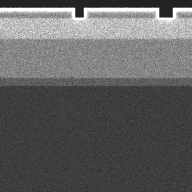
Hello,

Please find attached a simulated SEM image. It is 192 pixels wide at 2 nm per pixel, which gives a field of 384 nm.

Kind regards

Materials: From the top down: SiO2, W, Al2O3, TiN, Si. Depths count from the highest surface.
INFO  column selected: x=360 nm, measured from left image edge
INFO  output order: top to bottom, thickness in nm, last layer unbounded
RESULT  SiO2 20, W 42, Al2O3 78, TiN 16, Si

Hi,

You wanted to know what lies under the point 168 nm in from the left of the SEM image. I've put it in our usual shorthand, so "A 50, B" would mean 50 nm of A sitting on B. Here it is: SiO2 20, W 42, Al2O3 78, TiN 16, Si